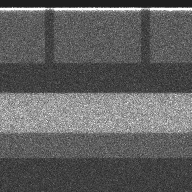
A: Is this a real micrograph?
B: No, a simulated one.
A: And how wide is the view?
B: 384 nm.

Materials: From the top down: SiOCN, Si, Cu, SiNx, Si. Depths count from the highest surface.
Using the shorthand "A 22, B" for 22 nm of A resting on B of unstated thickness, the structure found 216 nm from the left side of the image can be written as SiOCN 110, Si 60, Cu 80, SiNx 50, Si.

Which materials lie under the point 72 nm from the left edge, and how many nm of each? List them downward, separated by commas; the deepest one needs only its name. SiOCN 110, Si 60, Cu 80, SiNx 50, Si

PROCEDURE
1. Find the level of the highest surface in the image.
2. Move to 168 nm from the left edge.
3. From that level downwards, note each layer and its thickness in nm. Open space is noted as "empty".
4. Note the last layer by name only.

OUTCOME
SiOCN 110, Si 60, Cu 80, SiNx 50, Si